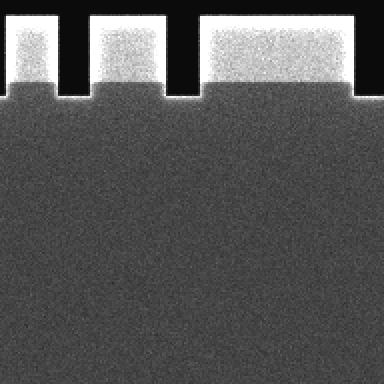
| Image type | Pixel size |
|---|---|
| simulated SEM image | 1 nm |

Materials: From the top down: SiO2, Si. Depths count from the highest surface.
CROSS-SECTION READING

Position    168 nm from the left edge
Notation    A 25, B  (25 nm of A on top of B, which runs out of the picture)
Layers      empty 80, Si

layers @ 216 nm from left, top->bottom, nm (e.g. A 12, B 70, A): SiO2 66, Si